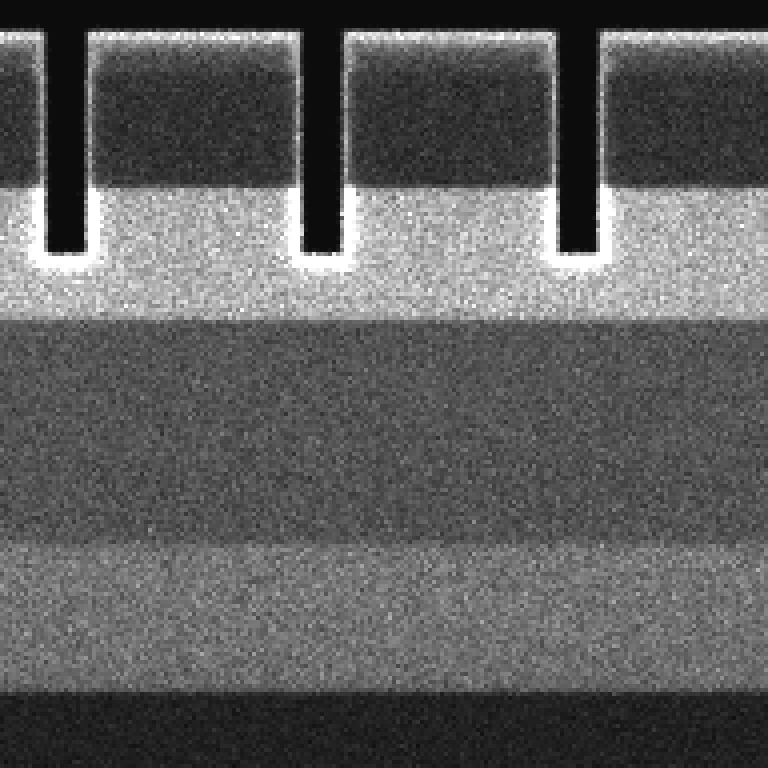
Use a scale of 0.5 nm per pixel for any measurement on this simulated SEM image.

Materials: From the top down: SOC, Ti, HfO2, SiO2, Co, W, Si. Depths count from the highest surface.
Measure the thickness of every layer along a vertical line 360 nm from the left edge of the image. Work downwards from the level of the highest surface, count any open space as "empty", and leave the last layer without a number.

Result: SOC 20, Ti 58, HfO2 66, SiO2 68, Co 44, W 74, Si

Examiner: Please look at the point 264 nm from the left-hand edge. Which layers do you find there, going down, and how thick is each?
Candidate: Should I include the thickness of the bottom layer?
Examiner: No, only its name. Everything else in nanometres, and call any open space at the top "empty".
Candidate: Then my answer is SOC 20, Ti 58, HfO2 66, SiO2 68, Co 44, W 74, Si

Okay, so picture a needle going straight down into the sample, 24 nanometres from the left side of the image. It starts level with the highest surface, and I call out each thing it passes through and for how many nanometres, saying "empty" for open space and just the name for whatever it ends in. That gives empty 112, HfO2 32, SiO2 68, Co 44, W 74, Si